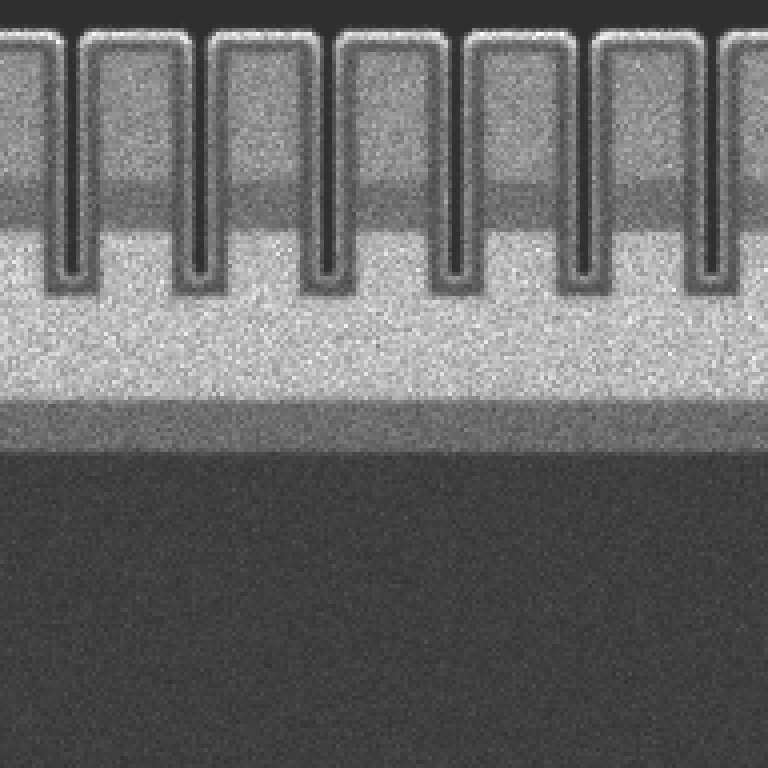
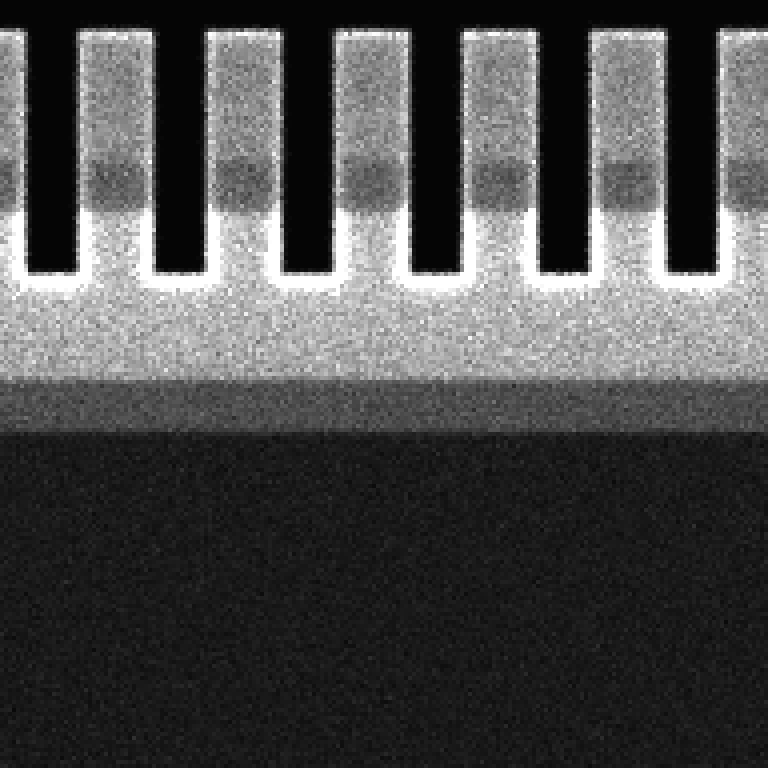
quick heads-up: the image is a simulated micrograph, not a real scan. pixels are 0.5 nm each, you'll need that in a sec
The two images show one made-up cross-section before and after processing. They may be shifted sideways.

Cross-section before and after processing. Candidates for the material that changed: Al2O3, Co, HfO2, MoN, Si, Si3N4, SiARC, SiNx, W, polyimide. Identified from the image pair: SiNx (removed).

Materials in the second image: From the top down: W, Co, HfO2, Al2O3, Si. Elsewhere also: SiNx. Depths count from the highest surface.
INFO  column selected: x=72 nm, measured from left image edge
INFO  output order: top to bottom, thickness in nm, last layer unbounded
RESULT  W 64, Co 26, HfO2 84, Al2O3 26, Si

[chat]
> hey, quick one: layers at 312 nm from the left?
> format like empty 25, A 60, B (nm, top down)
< W 64, Co 26, HfO2 84, Al2O3 26, Si